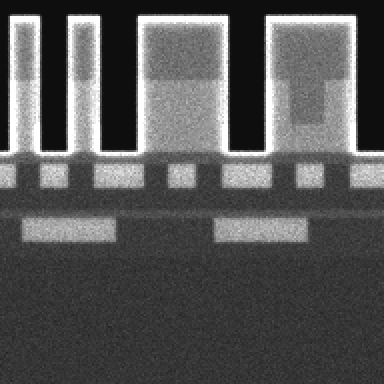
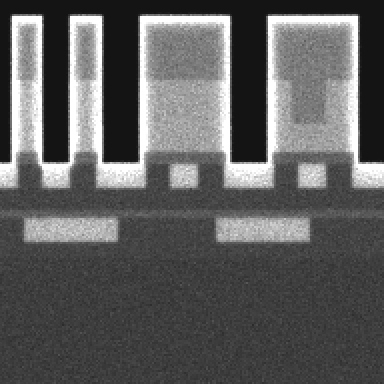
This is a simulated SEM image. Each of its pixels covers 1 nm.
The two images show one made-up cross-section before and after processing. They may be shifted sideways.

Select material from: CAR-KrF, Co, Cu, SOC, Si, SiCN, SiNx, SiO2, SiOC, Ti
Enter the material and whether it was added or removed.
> SiCN / removed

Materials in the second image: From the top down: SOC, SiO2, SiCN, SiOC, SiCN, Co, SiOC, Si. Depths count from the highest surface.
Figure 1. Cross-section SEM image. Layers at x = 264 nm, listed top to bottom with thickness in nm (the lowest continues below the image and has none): empty 148, Co 24, SiOC 22, SiCN 8, Co 24, SiOC 16, Si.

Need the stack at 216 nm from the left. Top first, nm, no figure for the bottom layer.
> SOC 64, SiO2 72, SiCN 12, SiOC 46, SiCN 8, Co 24, SiOC 16, Si